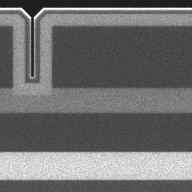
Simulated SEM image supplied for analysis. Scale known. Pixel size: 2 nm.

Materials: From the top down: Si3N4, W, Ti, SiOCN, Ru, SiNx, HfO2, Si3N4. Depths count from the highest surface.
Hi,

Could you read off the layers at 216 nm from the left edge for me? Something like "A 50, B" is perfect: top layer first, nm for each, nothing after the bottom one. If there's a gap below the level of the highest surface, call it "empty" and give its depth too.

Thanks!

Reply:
Si3N4 12, W 24, Ti 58, SiOCN 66, Ru 50, SiNx 78, HfO2 56, Si3N4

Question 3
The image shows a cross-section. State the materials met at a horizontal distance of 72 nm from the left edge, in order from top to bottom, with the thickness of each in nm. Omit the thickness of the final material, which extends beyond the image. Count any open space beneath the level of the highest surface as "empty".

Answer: empty 14, Si3N4 136, W 24, Ru 36, SiNx 78, HfO2 56, Si3N4